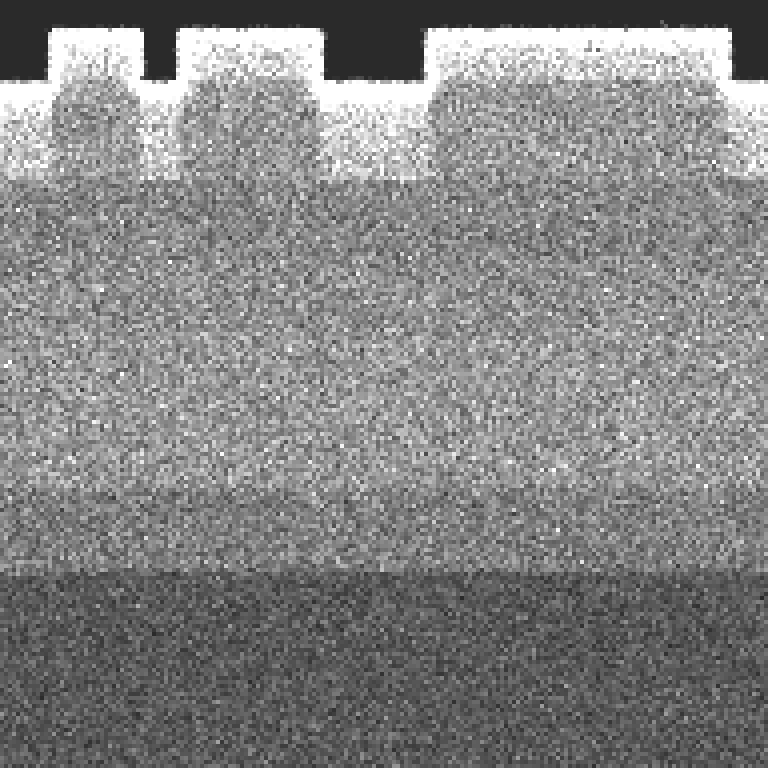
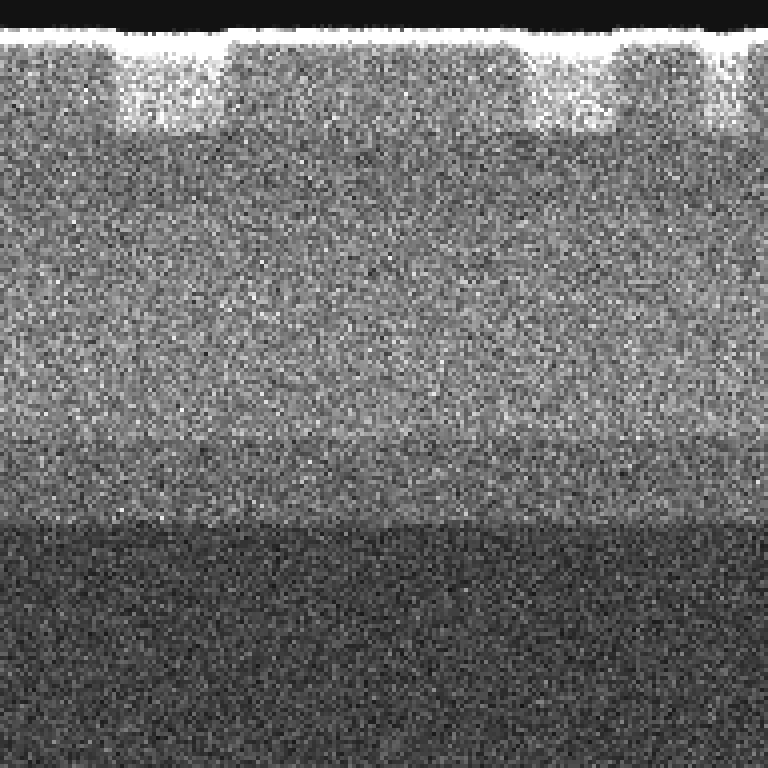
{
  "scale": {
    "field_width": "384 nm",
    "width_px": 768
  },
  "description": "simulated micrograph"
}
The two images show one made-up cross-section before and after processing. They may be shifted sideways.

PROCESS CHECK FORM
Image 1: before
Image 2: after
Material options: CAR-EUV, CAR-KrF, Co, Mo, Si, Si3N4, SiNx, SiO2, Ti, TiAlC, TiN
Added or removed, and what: removed, Co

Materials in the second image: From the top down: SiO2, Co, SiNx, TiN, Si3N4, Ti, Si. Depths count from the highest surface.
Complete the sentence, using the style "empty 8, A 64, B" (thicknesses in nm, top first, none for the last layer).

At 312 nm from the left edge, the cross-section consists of Si3N4 50, SiNx 40, TiN 34, Si3N4 80, Ti 42, Si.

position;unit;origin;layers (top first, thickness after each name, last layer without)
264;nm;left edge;empty 2, SiO2 24, Co 24, SiNx 40, TiN 34, Si3N4 80, Ti 42, Si